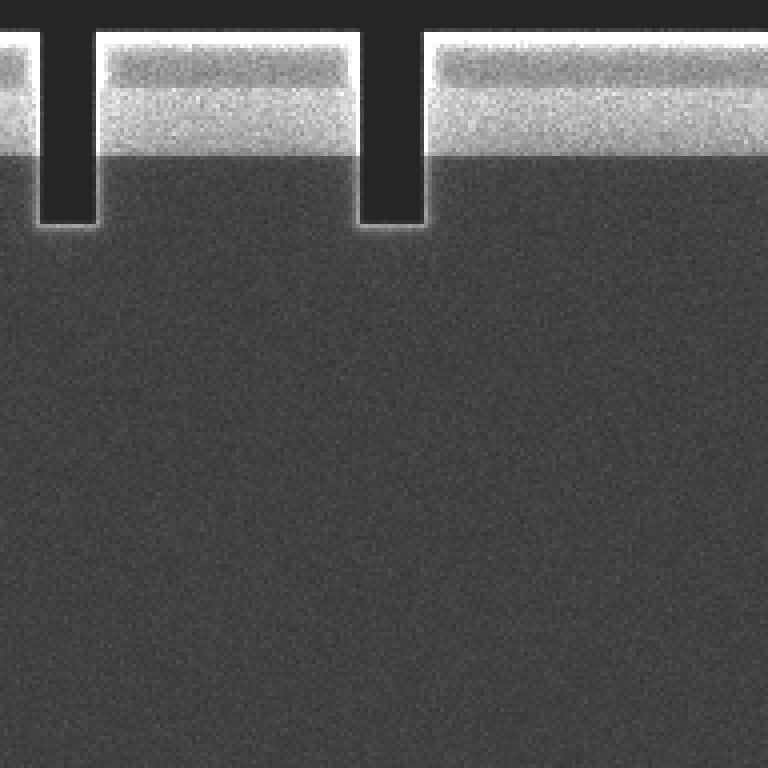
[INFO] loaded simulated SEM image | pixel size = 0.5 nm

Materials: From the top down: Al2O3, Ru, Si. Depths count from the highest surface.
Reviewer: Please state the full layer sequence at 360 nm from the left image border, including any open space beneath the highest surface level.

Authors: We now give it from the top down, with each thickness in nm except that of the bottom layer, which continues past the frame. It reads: Al2O3 28, Ru 34, Si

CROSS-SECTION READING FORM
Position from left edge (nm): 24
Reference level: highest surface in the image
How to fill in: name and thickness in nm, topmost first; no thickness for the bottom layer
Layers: empty 96, Si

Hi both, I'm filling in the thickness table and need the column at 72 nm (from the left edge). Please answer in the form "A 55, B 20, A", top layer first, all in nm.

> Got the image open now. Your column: Al2O3 28, Ru 34, Si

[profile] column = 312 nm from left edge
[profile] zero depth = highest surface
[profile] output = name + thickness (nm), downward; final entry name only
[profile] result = Al2O3 28, Ru 34, Si